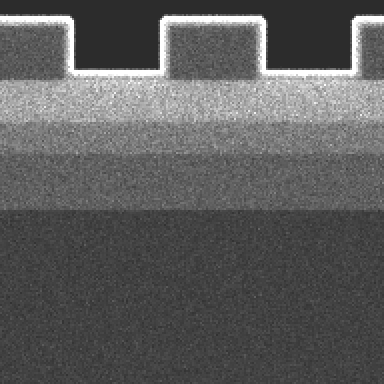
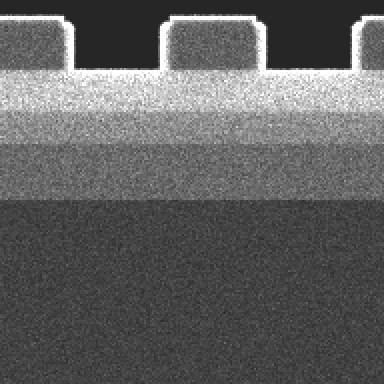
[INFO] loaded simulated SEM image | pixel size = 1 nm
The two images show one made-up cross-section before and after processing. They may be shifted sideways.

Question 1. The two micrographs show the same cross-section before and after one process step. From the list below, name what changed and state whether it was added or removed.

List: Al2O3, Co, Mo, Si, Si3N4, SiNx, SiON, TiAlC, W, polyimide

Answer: Al2O3, removed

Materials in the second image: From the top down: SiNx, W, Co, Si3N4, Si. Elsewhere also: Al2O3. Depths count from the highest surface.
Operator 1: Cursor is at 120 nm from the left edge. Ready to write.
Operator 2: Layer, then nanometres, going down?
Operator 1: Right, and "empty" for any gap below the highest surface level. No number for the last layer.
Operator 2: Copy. empty 54, W 42, Co 32, Si3N4 56, Si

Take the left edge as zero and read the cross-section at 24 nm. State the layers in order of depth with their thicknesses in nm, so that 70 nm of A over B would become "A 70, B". SiNx 54, W 42, Co 32, Si3N4 56, Si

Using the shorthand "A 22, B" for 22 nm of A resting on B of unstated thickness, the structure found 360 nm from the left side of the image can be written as empty 6, Al2O3 48, W 42, Co 32, Si3N4 56, Si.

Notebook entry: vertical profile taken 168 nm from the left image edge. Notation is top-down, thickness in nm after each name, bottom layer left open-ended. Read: empty 6, Al2O3 48, W 42, Co 32, Si3N4 56, Si